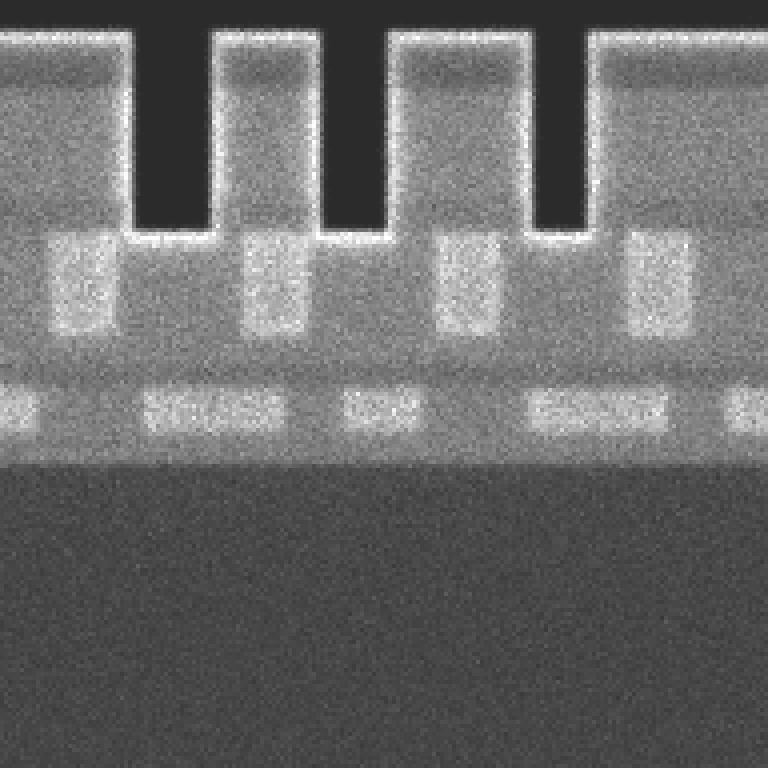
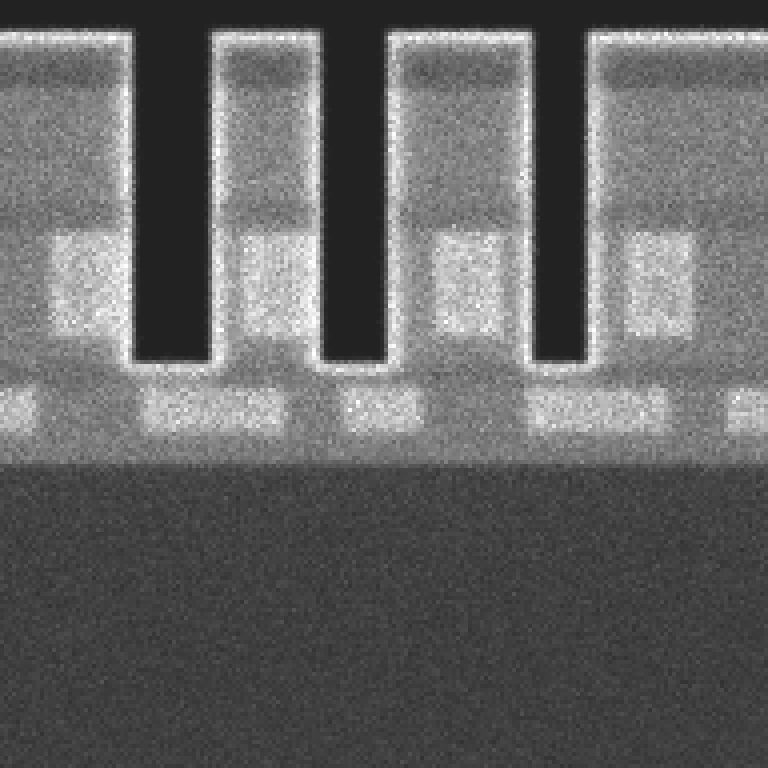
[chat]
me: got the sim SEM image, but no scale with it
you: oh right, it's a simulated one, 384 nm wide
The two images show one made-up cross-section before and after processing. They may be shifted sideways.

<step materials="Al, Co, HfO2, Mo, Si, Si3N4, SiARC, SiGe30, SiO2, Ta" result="removed SiO2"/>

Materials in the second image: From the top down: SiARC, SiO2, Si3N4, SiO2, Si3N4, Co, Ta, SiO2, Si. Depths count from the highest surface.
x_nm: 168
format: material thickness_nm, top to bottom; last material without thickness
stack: empty 166, Si3N4 12, SiO2 38, Si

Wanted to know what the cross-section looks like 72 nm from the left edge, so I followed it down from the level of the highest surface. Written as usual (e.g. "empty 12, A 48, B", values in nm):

empty 166, Si3N4 12, Ta 22, SiO2 16, Si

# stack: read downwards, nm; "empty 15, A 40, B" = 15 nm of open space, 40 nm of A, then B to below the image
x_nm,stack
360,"SiARC 28, SiO2 56, Si3N4 16, SiO2 66, Si3N4 12, SiO2 38, Si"